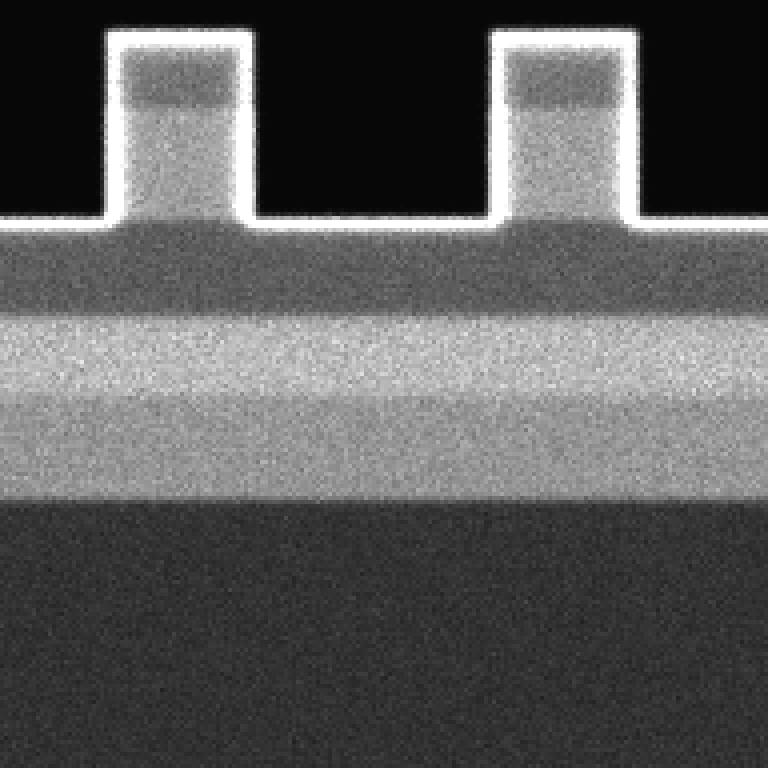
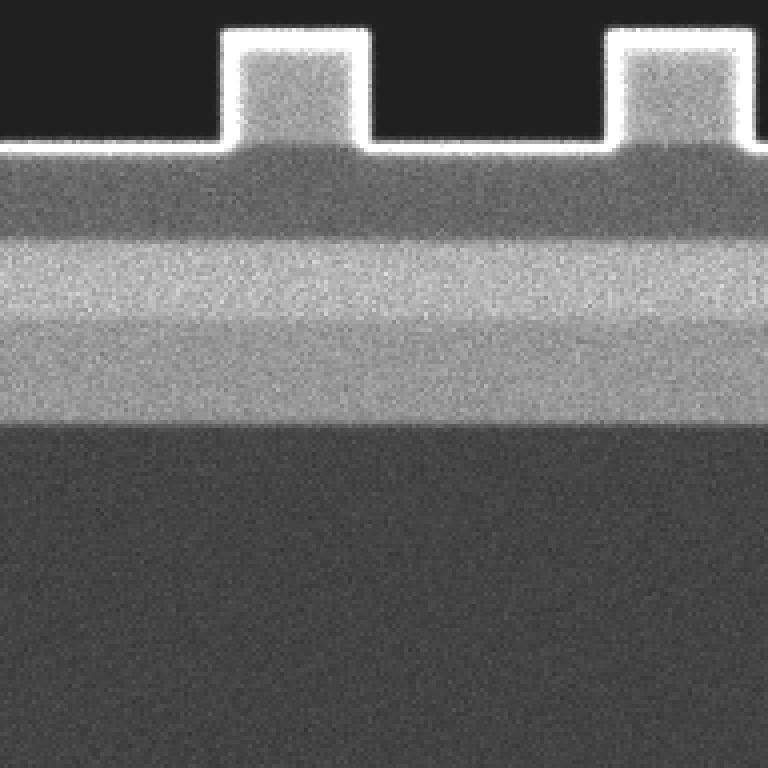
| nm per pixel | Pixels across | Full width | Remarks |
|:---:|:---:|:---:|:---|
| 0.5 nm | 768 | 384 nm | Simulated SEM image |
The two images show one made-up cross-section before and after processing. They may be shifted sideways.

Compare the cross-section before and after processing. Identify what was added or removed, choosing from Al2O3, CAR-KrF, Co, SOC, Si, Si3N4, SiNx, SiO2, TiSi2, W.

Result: SOC removed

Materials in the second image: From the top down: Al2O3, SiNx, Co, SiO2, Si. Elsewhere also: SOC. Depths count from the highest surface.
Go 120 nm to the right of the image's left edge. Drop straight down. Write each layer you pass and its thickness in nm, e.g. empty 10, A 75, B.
Al2O3 56, SiNx 48, Co 40, SiO2 52, Si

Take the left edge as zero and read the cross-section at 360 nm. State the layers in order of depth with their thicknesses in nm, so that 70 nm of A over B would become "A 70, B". Al2O3 56, SiNx 48, Co 40, SiO2 52, Si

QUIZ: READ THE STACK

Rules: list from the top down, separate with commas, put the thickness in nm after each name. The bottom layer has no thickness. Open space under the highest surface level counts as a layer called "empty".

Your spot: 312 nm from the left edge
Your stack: Al2O3 56, SiNx 48, Co 40, SiO2 52, Si